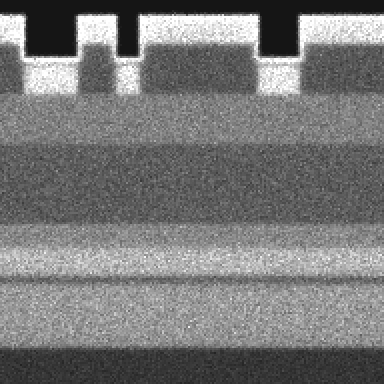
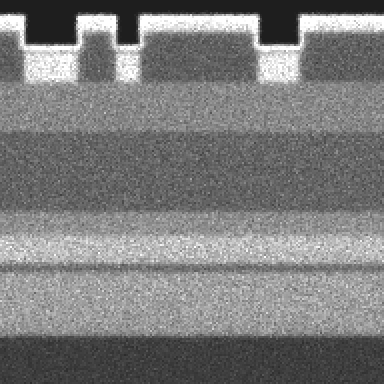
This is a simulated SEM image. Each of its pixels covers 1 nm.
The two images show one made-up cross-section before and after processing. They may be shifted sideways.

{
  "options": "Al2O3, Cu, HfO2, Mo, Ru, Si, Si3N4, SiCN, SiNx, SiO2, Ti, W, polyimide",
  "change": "removed",
  "material": "W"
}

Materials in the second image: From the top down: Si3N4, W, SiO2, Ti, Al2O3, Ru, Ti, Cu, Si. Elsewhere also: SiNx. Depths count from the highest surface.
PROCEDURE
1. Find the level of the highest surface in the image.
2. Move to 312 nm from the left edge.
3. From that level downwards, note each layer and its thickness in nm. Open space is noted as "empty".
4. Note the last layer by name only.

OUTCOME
W 16, SiNx 50, SiO2 50, Ti 80, Al2O3 24, Ru 28, Ti 8, Cu 64, Si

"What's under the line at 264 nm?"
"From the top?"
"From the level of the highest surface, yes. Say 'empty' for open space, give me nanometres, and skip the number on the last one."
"empty 30, Si3N4 8, W 28, SiO2 50, Ti 80, Al2O3 24, Ru 28, Ti 8, Cu 64, Si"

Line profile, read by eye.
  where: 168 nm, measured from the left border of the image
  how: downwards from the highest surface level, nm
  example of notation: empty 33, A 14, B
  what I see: W 16, SiNx 50, SiO2 50, Ti 80, Al2O3 24, Ru 28, Ti 8, Cu 64, Si